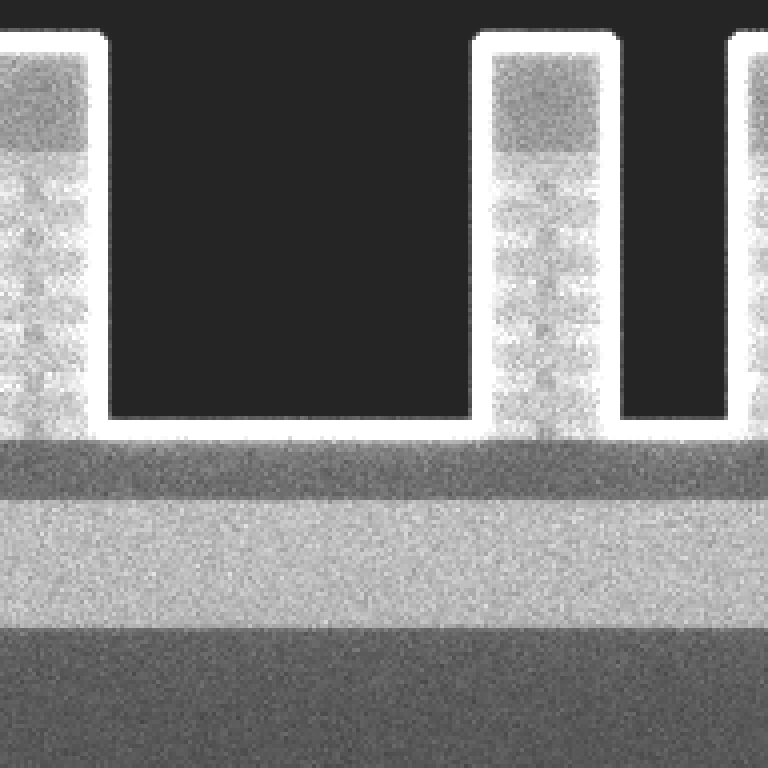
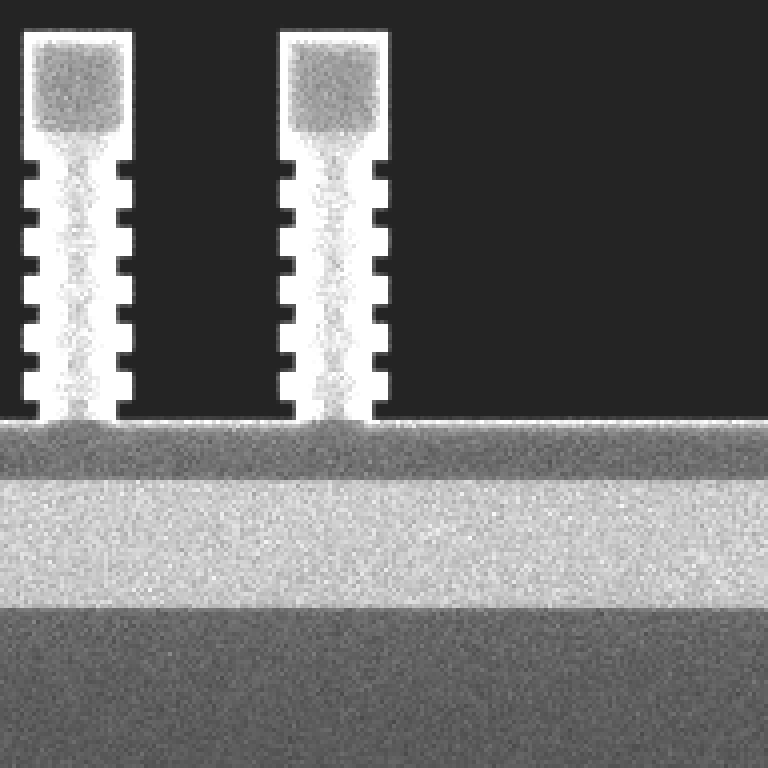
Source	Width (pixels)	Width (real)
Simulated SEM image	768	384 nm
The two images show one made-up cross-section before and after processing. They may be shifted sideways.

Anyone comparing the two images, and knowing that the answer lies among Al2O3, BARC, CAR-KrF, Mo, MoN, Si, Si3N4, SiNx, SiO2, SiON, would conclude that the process removed Al2O3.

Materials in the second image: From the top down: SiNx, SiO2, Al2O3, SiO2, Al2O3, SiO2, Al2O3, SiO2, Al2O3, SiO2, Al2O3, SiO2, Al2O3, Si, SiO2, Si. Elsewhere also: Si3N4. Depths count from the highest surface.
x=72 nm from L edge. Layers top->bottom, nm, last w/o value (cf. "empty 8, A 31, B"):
empty 194, Si 30, SiO2 64, Si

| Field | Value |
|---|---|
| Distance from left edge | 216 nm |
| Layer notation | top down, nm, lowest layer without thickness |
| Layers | empty 194, Si 30, SiO2 64, Si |